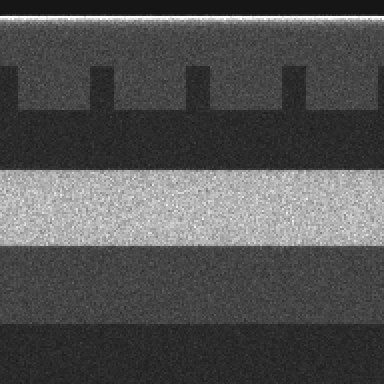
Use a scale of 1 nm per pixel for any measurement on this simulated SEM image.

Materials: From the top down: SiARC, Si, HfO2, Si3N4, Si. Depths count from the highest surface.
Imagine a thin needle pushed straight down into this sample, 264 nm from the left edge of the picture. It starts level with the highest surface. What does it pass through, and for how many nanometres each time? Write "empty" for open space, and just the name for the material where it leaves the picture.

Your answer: SiARC 94, Si 60, HfO2 76, Si3N4 78, Si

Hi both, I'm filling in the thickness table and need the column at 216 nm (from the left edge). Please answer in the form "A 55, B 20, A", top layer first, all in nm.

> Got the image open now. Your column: SiARC 94, Si 60, HfO2 76, Si3N4 78, Si